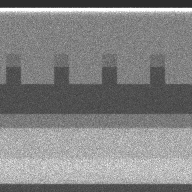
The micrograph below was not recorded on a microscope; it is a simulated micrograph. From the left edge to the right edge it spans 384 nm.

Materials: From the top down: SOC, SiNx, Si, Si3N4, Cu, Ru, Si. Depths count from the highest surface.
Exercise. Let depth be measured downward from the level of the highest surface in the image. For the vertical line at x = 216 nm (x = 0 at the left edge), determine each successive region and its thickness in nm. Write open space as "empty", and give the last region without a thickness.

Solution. SOC 92, SiNx 26, Si 94, Si3N4 28, Cu 62, Ru 50, Si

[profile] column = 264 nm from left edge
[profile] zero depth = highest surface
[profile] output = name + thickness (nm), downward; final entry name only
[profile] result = SOC 152, Si 60, Si3N4 28, Cu 62, Ru 50, Si